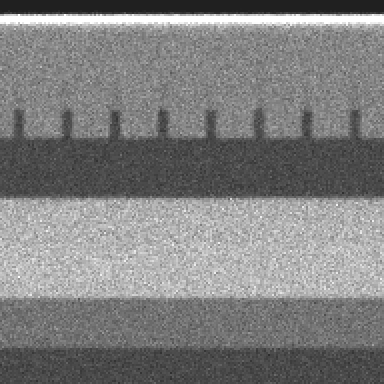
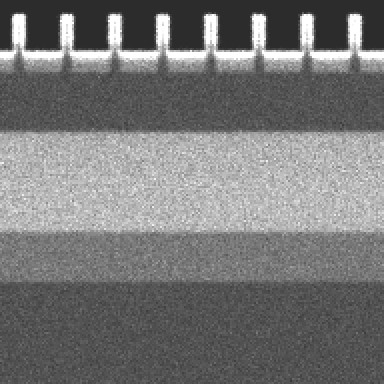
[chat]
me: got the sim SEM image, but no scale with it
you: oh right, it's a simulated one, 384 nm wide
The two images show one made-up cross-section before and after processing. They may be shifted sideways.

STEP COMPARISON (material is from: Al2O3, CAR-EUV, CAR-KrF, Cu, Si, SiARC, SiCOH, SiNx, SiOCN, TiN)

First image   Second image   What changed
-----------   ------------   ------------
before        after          SiARC, removed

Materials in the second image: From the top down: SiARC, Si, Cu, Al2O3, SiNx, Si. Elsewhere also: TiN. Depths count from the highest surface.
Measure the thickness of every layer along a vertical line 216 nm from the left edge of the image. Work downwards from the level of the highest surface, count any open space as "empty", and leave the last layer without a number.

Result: empty 36, SiARC 20, Si 60, Cu 46, Al2O3 54, SiNx 50, Si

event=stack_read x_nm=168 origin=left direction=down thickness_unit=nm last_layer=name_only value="empty 36, SiARC 20, Si 60, Cu 46, Al2O3 54, SiNx 50, Si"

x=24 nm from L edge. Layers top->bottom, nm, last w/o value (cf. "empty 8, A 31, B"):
empty 36, SiARC 20, Si 60, Cu 46, Al2O3 54, SiNx 50, Si